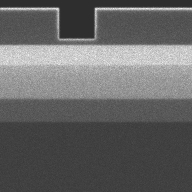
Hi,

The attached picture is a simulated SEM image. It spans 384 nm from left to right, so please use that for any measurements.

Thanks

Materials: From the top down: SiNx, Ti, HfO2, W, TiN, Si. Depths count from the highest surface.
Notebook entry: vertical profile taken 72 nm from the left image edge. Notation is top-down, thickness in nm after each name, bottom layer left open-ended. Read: SiNx 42, Ti 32, HfO2 40, W 68, TiN 46, Si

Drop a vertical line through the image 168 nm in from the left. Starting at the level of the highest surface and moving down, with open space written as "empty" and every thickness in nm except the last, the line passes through empty 62, Ti 12, HfO2 40, W 68, TiN 46, Si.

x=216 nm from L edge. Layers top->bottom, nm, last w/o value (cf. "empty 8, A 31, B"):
SiNx 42, Ti 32, HfO2 40, W 68, TiN 46, Si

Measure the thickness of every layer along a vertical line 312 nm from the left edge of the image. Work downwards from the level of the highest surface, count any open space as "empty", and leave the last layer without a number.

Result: SiNx 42, Ti 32, HfO2 40, W 68, TiN 46, Si